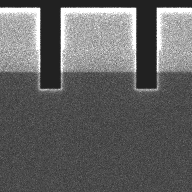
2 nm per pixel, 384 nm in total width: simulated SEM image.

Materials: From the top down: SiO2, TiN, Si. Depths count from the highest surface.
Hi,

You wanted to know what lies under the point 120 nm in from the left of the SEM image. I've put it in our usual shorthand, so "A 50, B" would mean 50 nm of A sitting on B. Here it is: empty 162, Si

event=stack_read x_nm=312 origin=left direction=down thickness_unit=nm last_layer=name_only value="empty 162, Si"